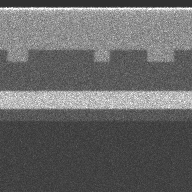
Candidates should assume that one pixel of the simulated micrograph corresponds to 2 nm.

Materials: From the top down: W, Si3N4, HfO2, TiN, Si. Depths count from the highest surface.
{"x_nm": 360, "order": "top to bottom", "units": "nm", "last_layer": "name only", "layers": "W 84, Si3N4 82, HfO2 36, TiN 24, Si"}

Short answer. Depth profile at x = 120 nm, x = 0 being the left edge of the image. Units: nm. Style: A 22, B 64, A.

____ W 84, Si3N4 82, HfO2 36, TiN 24, Si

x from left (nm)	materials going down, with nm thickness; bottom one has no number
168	W 84, Si3N4 82, HfO2 36, TiN 24, Si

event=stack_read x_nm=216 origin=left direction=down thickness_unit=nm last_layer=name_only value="W 108, Si3N4 58, HfO2 36, TiN 24, Si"